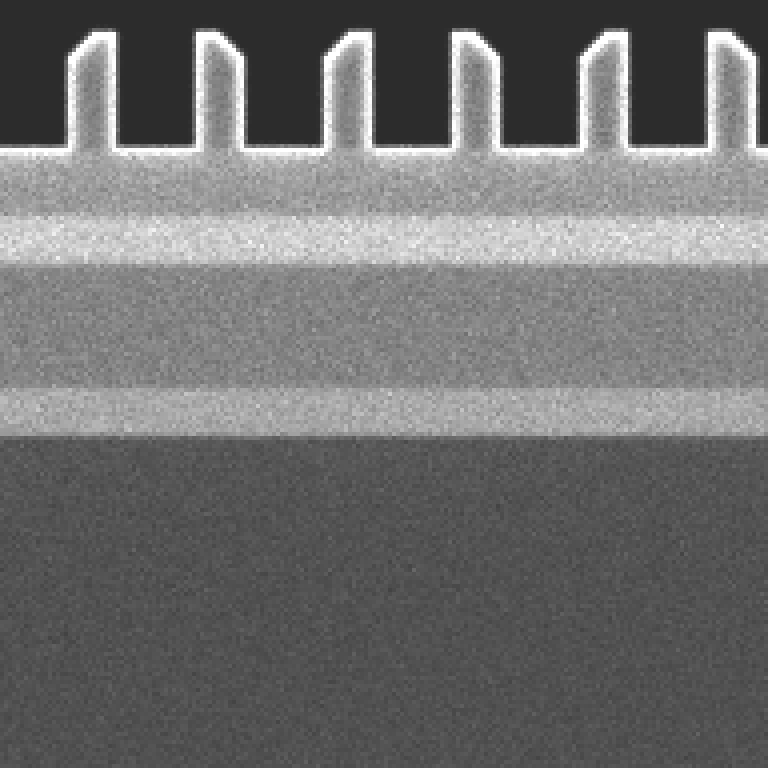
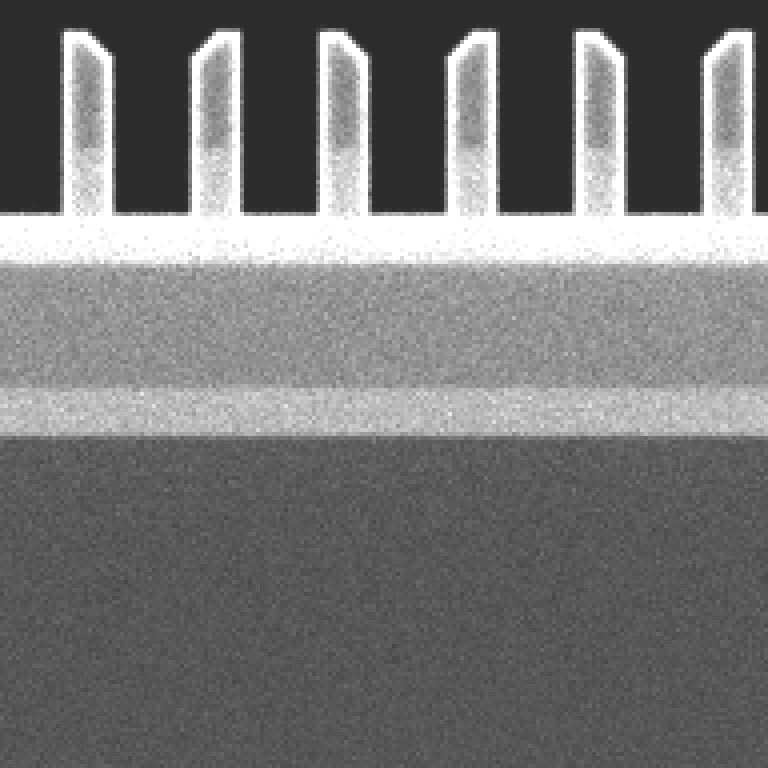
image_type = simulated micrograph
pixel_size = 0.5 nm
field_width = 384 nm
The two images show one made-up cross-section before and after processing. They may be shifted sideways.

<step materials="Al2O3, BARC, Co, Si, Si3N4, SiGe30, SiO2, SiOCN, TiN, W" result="removed TiN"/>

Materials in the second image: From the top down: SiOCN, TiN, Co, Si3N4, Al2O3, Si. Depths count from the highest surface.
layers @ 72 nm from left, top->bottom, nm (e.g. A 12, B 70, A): empty 92, Co 24, Si3N4 62, Al2O3 24, Si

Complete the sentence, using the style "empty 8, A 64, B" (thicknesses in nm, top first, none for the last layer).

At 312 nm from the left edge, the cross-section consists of empty 92, Co 24, Si3N4 62, Al2O3 24, Si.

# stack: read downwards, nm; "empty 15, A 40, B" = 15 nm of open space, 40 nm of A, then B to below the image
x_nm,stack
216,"empty 92, Co 24, Si3N4 62, Al2O3 24, Si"